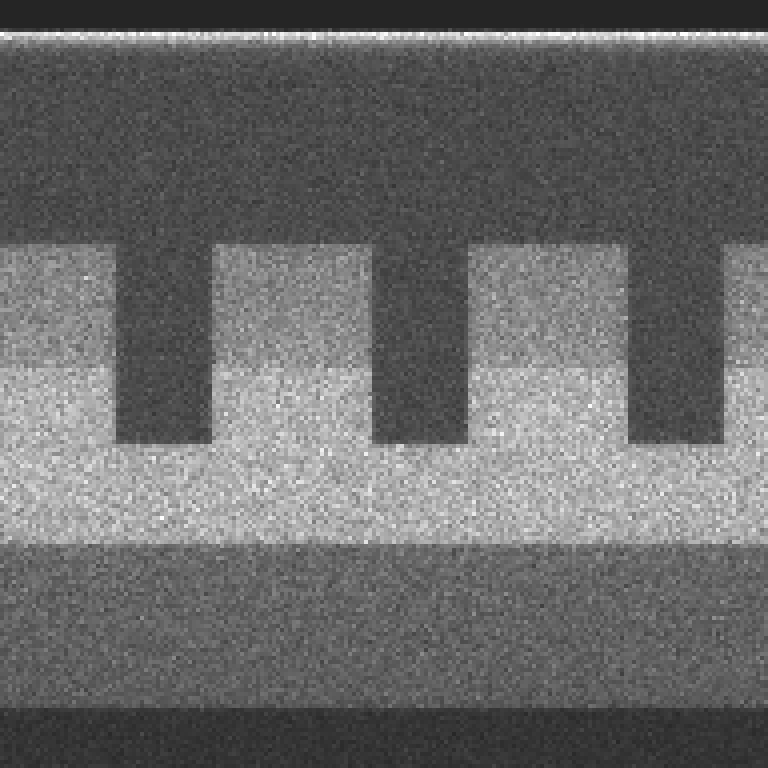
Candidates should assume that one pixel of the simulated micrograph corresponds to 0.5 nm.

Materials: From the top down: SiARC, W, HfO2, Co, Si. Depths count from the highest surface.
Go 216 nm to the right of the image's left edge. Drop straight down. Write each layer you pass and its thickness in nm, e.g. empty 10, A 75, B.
SiARC 206, HfO2 50, Co 82, Si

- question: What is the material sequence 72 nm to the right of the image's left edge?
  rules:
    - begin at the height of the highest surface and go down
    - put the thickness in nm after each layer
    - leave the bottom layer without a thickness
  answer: SiARC 206, HfO2 50, Co 82, Si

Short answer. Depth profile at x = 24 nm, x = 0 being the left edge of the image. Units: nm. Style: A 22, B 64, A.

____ SiARC 106, W 62, HfO2 88, Co 82, Si